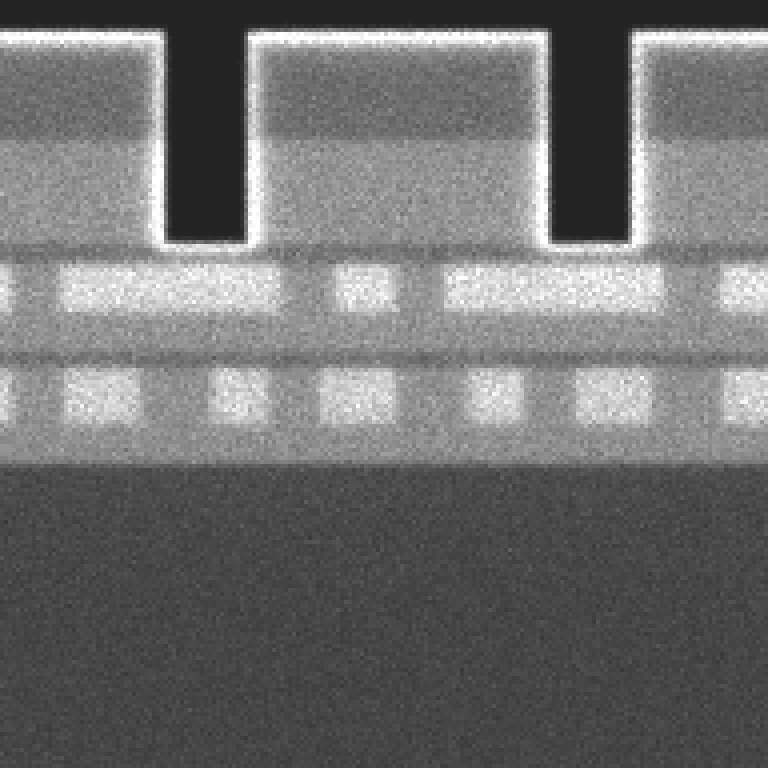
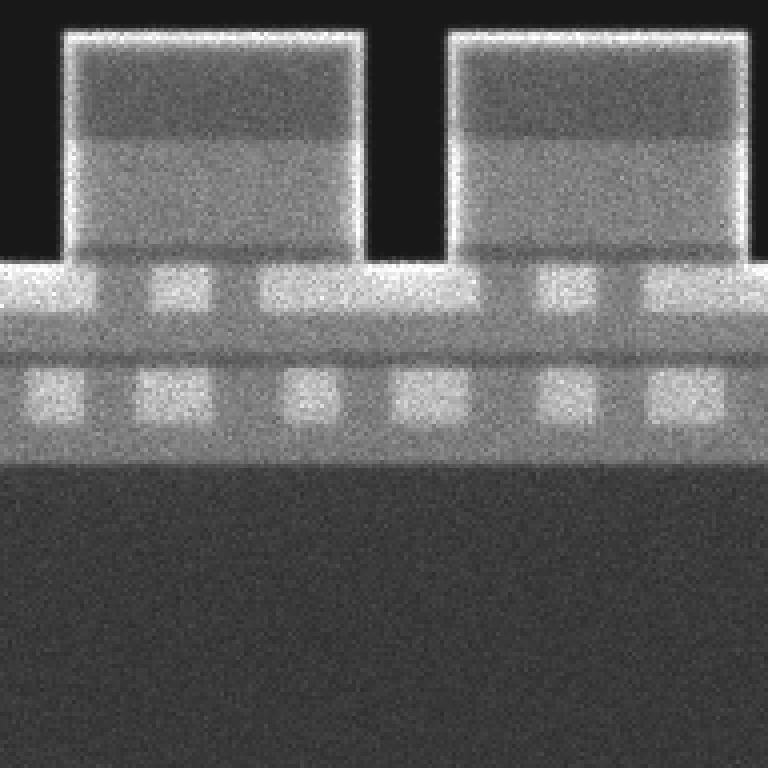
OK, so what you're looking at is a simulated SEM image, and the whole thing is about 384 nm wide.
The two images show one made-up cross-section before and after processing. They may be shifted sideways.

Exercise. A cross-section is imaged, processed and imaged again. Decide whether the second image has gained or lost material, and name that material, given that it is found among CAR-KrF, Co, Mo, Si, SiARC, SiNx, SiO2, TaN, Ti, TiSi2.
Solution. removed: SiNx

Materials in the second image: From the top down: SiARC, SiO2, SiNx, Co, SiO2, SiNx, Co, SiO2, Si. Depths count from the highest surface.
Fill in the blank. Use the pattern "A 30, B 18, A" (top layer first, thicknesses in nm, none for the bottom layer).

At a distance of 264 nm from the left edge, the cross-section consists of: SiARC 54, SiO2 52, SiNx 10, SiO2 44, SiNx 8, SiO2 48, Si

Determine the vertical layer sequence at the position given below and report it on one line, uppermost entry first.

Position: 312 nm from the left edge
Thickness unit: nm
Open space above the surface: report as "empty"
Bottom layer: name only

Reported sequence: SiARC 54, SiO2 52, SiNx 10, SiO2 44, SiNx 8, SiO2 48, Si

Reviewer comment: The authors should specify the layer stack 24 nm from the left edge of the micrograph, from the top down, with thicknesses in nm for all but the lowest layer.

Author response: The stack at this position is empty 116, Co 24, SiO2 20, SiNx 8, Co 28, SiO2 20, Si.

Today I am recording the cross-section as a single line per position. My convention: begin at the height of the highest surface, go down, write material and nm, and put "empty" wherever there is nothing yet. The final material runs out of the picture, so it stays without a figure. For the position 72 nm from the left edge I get SiARC 54, SiO2 52, SiNx 10, SiO2 44, SiNx 8, Co 28, SiO2 20, Si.